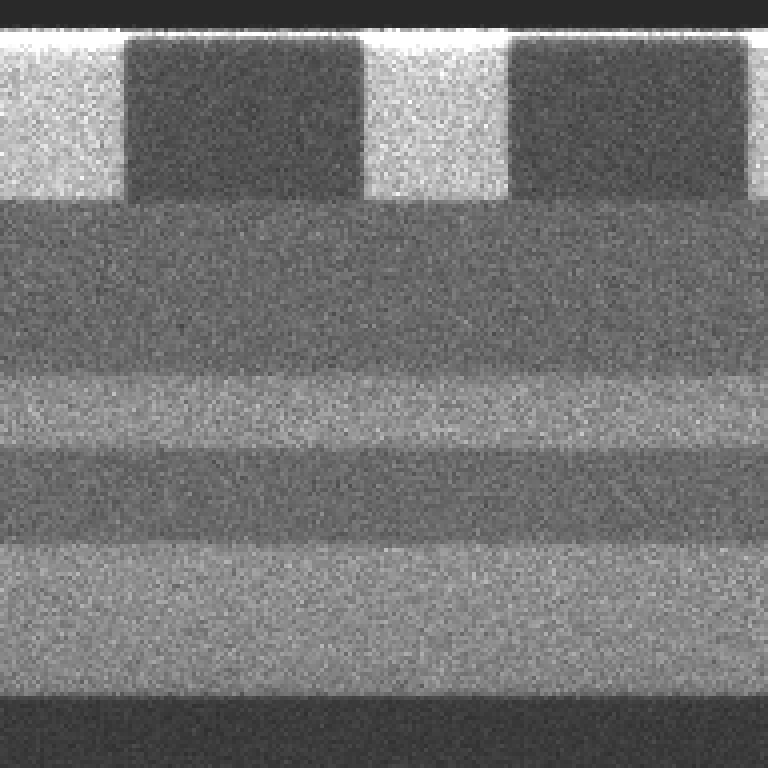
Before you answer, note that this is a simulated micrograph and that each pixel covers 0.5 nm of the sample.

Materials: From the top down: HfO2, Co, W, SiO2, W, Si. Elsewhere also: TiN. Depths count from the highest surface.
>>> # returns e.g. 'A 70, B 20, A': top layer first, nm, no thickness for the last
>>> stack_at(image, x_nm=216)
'HfO2 84, Co 88, W 36, SiO2 48, W 76, Si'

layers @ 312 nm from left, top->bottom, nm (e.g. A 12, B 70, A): TiN 84, Co 88, W 36, SiO2 48, W 76, Si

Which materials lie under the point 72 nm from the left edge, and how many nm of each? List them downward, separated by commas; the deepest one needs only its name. TiN 84, Co 88, W 36, SiO2 48, W 76, Si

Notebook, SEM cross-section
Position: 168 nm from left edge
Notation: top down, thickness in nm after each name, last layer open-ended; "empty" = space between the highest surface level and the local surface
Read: TiN 84, Co 88, W 36, SiO2 48, W 76, Si